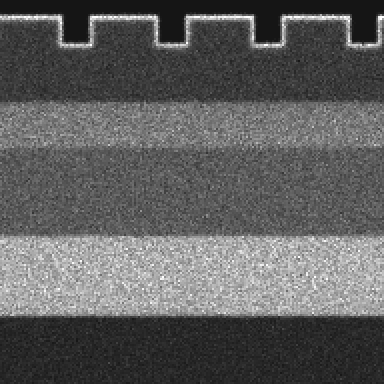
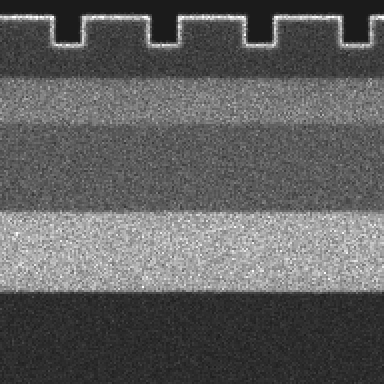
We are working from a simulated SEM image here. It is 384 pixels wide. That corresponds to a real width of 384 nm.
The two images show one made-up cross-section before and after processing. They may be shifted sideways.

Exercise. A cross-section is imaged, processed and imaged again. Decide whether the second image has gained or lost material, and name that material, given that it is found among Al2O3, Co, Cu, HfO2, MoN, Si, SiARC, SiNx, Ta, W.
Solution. removed: SiNx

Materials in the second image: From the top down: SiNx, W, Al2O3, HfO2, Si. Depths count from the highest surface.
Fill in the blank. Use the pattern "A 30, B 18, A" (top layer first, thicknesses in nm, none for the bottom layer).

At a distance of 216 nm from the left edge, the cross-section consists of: SiNx 62, W 46, Al2O3 88, HfO2 80, Si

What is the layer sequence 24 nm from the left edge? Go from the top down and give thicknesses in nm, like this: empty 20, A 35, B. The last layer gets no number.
SiNx 62, W 46, Al2O3 88, HfO2 80, Si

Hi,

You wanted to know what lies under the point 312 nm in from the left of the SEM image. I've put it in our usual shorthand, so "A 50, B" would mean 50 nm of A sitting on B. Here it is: SiNx 62, W 46, Al2O3 88, HfO2 80, Si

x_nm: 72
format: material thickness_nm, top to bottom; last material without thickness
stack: empty 28, SiNx 34, W 46, Al2O3 88, HfO2 80, Si